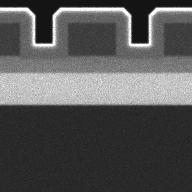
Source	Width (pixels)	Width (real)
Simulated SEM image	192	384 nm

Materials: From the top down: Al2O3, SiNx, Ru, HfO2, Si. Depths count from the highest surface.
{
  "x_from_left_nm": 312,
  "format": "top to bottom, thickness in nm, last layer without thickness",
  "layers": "Al2O3 102, Ru 28, HfO2 64, Si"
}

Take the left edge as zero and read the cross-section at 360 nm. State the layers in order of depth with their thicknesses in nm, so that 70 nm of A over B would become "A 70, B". Al2O3 30, SiNx 66, Ru 34, HfO2 64, Si